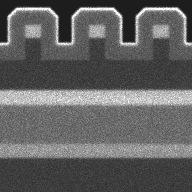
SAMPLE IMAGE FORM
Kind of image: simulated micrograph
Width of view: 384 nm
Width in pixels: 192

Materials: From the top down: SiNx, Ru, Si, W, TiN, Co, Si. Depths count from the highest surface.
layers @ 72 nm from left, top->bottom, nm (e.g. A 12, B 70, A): SiNx 34, Ru 26, Si 104, W 30, TiN 78, Co 28, Si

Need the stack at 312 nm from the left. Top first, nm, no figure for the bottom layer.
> SiNx 34, Ru 26, Si 104, W 30, TiN 78, Co 28, Si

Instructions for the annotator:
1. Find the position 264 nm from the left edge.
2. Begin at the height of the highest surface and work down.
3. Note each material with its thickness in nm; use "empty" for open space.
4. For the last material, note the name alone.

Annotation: empty 70, SiNx 34, Si 60, W 30, TiN 78, Co 28, Si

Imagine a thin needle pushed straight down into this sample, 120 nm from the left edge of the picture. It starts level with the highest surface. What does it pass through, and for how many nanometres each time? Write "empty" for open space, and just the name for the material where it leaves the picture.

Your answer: empty 70, SiNx 34, Si 60, W 30, TiN 78, Co 28, Si